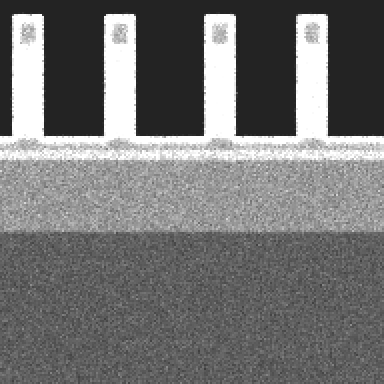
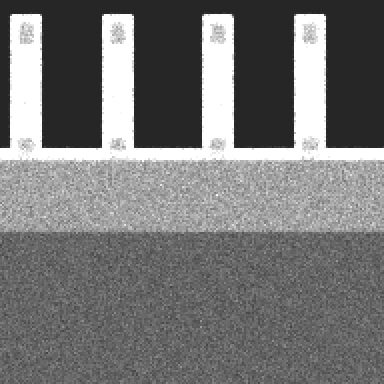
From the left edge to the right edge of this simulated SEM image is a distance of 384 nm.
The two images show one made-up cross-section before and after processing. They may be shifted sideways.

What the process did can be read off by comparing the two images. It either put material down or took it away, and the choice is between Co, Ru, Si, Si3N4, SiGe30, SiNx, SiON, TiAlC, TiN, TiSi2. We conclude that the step removed TiN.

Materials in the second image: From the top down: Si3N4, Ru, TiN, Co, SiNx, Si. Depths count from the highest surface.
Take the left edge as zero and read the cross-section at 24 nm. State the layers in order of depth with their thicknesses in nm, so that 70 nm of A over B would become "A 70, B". Si3N4 28, Ru 94, TiN 12, Co 10, SiNx 72, Si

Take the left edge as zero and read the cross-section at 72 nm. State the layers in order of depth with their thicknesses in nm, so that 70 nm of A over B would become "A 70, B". empty 134, Co 10, SiNx 72, Si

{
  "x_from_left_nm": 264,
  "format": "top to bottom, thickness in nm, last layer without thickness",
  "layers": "empty 134, Co 10, SiNx 72, Si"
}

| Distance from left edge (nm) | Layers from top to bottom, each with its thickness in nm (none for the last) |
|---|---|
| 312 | Si3N4 28, Ru 94, TiN 12, Co 10, SiNx 72, Si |